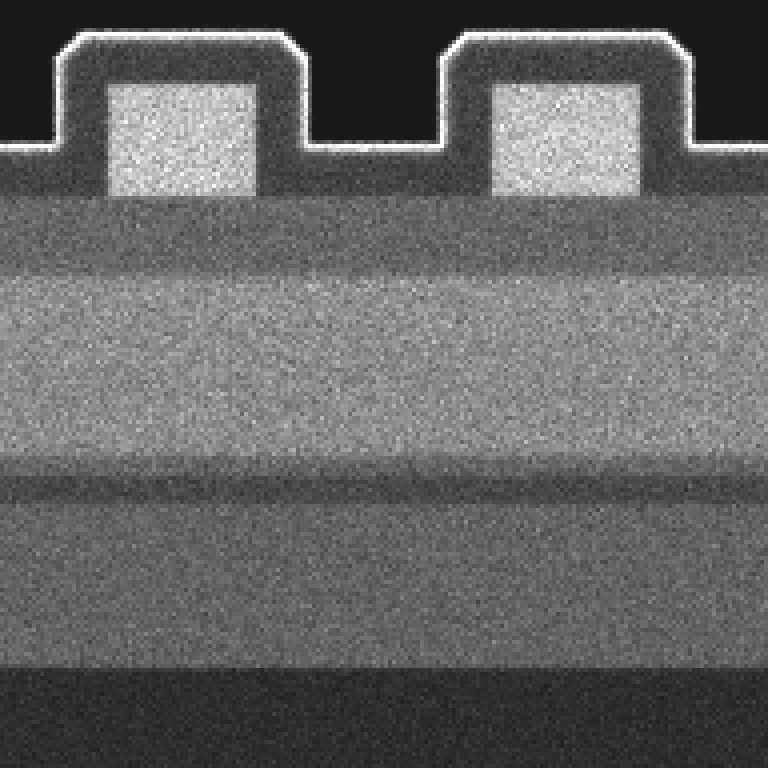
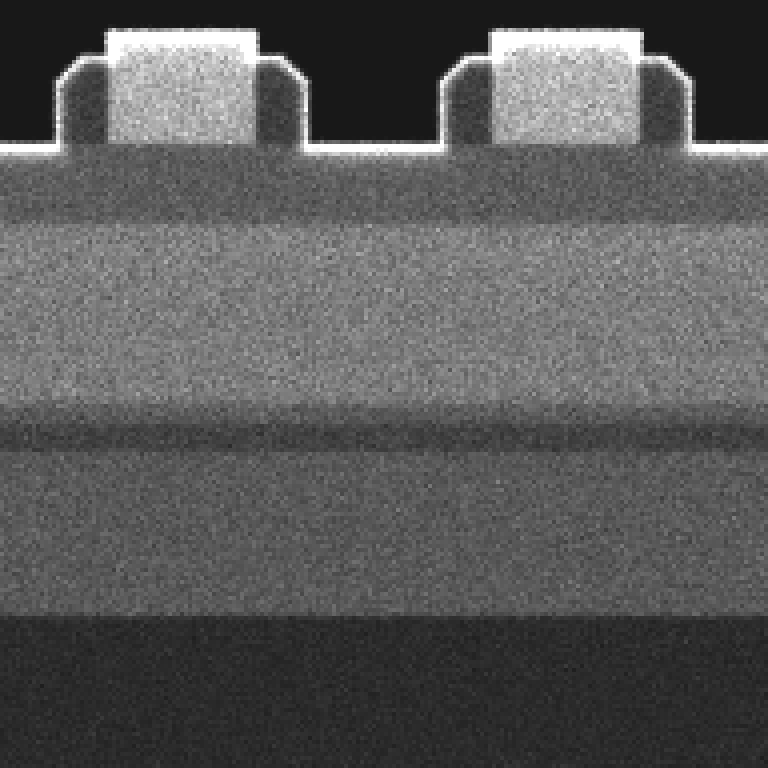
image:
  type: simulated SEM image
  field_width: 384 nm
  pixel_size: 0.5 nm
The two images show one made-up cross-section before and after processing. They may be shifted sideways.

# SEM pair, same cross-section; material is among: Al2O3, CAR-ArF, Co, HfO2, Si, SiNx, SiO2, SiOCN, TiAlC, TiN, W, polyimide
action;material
removed;SiNx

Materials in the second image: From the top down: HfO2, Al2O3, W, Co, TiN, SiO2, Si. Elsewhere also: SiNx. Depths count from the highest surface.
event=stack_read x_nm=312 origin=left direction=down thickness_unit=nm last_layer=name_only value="HfO2 56, Al2O3 40, W 90, Co 10, TiN 14, SiO2 82, Si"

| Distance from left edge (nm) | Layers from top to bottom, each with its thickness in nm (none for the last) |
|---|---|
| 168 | empty 56, Al2O3 40, W 90, Co 10, TiN 14, SiO2 82, Si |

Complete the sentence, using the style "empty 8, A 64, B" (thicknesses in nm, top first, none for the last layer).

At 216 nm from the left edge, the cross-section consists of empty 56, Al2O3 40, W 90, Co 10, TiN 14, SiO2 82, Si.